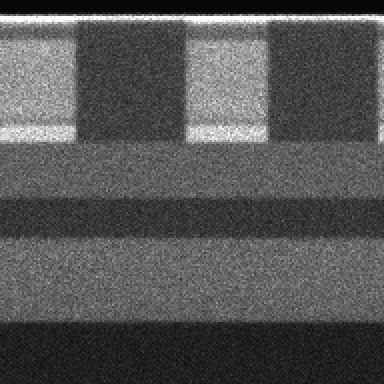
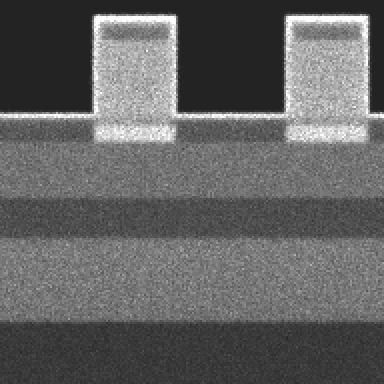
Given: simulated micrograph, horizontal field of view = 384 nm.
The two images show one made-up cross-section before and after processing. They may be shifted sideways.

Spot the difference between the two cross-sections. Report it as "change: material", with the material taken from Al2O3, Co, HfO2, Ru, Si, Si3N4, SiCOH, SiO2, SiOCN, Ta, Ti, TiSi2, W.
removed: Si3N4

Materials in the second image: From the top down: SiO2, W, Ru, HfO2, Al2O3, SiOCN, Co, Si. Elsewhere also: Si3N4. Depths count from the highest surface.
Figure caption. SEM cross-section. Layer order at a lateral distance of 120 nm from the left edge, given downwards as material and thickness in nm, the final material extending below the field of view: SiO2 24, W 76, Ru 10, HfO2 16, Al2O3 56, SiOCN 40, Co 84, Si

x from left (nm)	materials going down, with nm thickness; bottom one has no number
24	empty 98, Si3N4 28, Al2O3 56, SiOCN 40, Co 84, Si